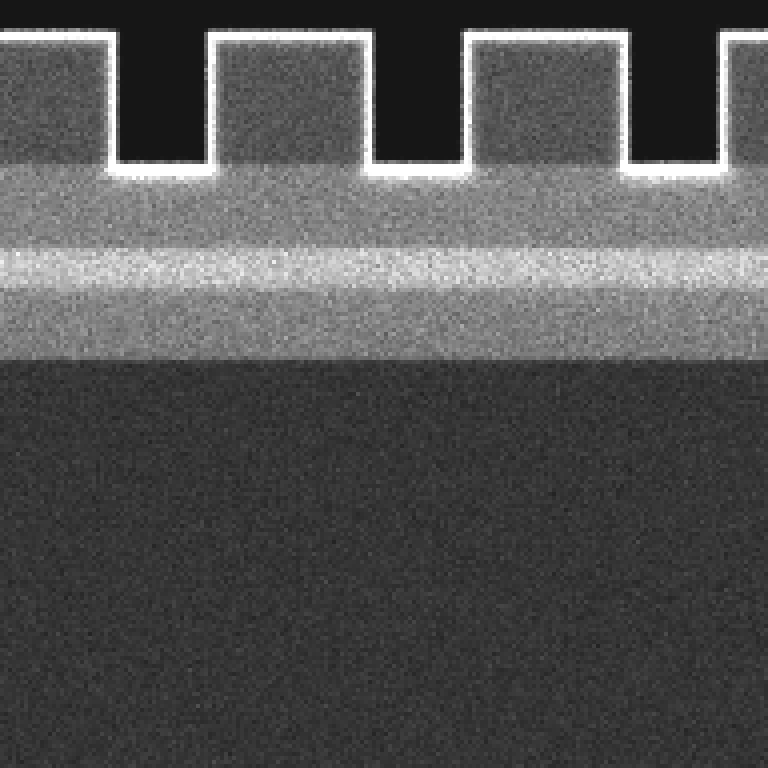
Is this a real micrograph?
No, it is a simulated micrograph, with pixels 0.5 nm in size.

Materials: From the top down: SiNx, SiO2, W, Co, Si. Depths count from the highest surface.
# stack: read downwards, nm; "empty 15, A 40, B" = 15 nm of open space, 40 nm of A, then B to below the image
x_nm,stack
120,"SiNx 66, SiO2 42, W 20, Co 36, Si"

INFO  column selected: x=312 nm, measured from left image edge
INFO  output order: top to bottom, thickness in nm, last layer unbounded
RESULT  SiNx 66, SiO2 42, W 20, Co 36, Si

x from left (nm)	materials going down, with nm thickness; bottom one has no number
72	empty 66, SiO2 42, W 20, Co 36, Si